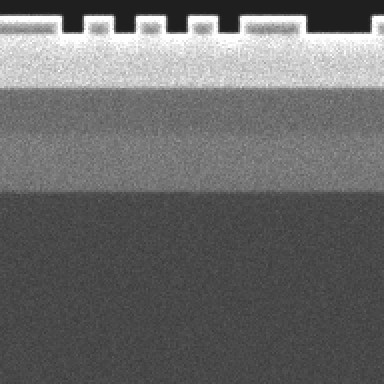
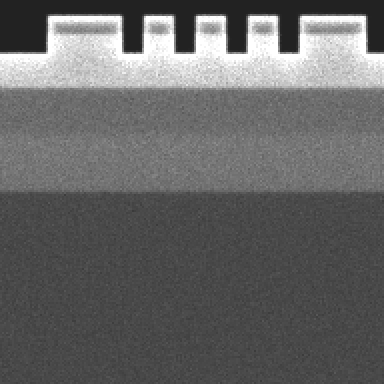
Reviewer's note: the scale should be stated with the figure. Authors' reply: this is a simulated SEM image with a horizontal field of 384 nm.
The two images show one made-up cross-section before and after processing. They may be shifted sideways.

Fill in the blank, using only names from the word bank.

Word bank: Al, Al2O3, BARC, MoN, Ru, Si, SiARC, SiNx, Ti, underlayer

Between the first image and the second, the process removed Ru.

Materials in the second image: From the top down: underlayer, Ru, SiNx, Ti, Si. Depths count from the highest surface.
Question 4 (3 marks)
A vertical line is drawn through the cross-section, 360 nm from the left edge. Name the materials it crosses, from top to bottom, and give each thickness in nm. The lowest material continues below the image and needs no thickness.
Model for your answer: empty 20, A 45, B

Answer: underlayer 18, Ru 54, SiNx 46, Ti 58, Si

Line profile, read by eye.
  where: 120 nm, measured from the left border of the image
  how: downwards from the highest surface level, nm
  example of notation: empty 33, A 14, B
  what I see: underlayer 18, Ru 54, SiNx 46, Ti 58, Si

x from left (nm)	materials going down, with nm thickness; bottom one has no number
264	underlayer 18, Ru 54, SiNx 46, Ti 58, Si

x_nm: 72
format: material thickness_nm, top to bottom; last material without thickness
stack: underlayer 18, Ru 54, SiNx 46, Ti 58, Si